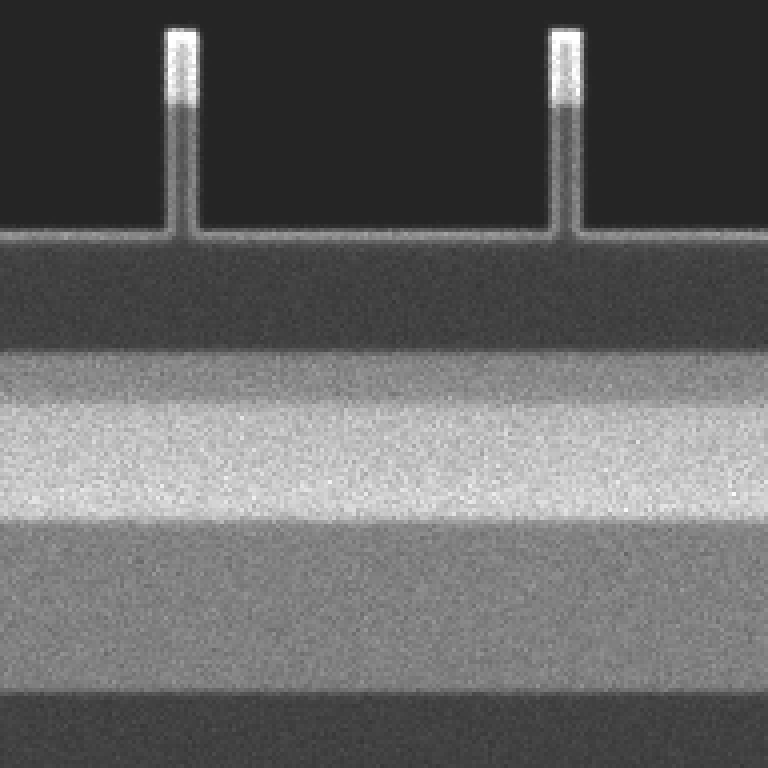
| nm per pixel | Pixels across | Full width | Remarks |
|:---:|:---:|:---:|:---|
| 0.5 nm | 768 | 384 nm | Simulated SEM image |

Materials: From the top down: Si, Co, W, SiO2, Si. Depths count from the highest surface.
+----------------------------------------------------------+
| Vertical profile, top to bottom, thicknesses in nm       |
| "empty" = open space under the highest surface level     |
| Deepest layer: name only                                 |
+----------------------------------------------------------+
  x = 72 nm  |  empty 100, Si 60, Co 26, W 58, SiO2 86, Si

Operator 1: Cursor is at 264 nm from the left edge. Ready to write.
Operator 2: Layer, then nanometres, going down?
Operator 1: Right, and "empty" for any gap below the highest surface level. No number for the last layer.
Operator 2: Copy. empty 100, Si 60, Co 26, W 58, SiO2 86, Si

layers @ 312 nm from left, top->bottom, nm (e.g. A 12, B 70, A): empty 100, Si 60, Co 26, W 58, SiO2 86, Si